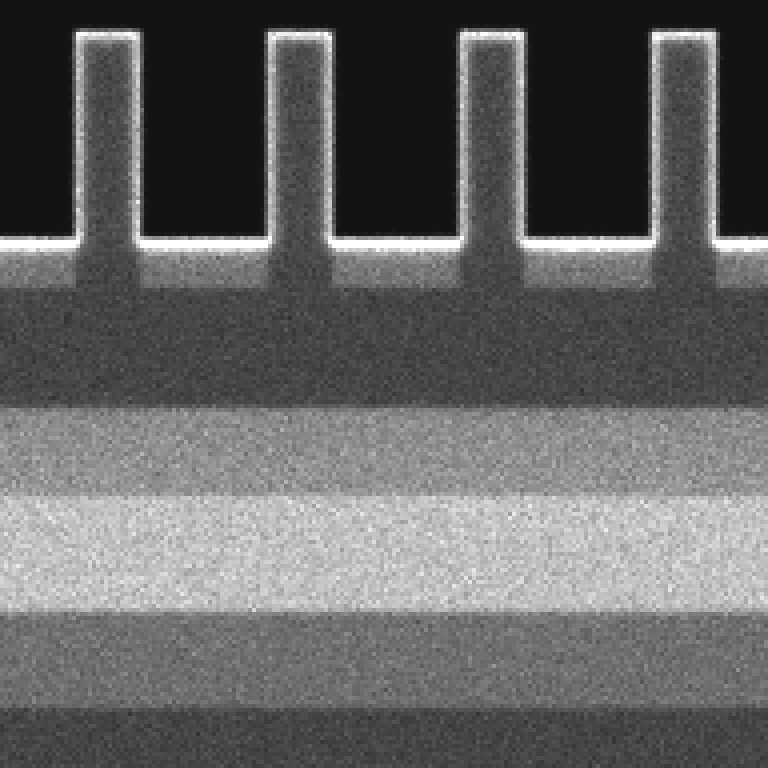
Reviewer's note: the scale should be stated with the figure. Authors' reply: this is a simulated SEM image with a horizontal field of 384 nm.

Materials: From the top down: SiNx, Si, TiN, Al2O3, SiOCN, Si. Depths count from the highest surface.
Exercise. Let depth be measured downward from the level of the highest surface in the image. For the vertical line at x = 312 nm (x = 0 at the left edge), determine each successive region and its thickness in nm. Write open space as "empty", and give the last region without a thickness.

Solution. empty 104, SiNx 24, Si 60, TiN 44, Al2O3 58, SiOCN 48, Si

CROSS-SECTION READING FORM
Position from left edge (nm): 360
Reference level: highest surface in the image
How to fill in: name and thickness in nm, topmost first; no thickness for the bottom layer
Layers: empty 104, SiNx 24, Si 60, TiN 44, Al2O3 58, SiOCN 48, Si